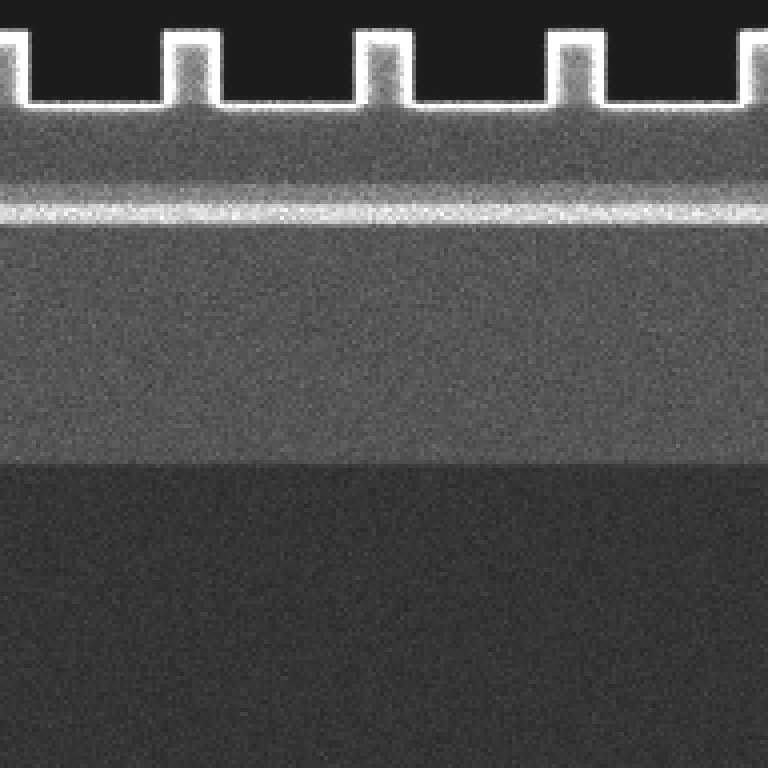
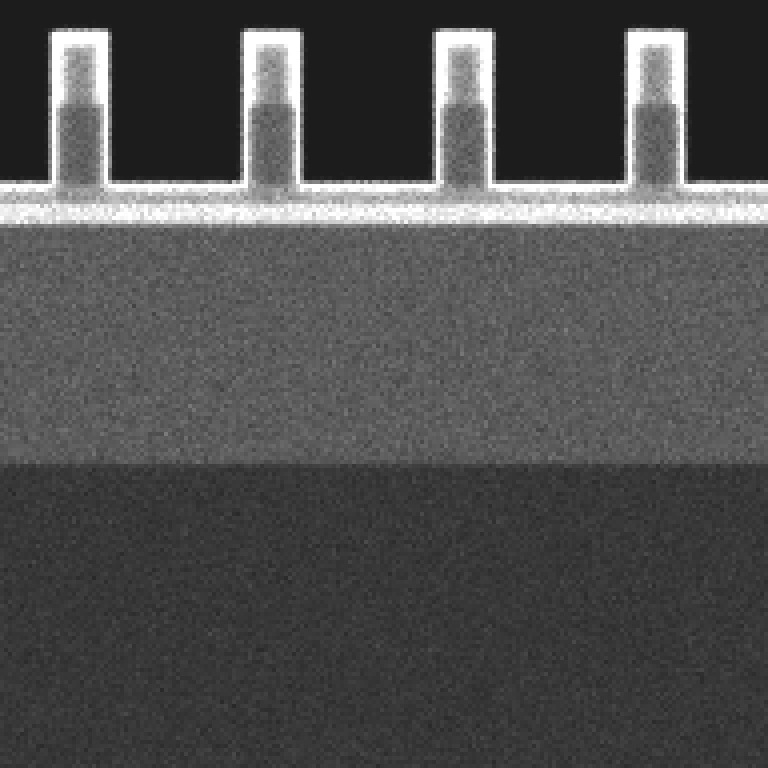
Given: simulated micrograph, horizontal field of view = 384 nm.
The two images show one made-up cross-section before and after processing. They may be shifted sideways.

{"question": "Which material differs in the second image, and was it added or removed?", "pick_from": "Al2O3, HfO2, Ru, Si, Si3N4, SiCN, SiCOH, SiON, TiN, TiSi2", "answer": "TiN, removed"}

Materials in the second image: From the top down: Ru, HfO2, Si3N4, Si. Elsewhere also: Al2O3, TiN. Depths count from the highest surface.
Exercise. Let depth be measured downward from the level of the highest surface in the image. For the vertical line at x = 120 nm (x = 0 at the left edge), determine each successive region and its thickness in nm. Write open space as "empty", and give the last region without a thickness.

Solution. empty 76, Ru 10, HfO2 10, Si3N4 120, Si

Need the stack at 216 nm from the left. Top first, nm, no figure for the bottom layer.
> empty 76, Ru 10, HfO2 10, Si3N4 120, Si